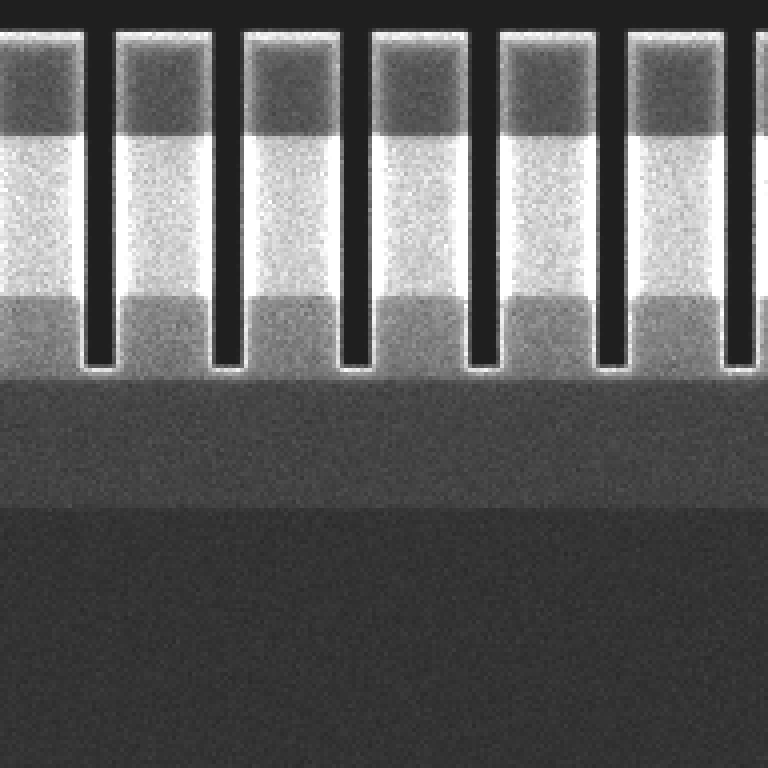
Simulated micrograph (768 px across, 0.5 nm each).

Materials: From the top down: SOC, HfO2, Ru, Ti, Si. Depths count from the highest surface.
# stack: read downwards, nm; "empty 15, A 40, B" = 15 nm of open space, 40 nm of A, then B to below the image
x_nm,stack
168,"SOC 52, HfO2 80, Ru 42, Ti 64, Si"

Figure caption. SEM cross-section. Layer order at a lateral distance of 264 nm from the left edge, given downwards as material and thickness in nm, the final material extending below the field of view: SOC 52, HfO2 80, Ru 42, Ti 64, Si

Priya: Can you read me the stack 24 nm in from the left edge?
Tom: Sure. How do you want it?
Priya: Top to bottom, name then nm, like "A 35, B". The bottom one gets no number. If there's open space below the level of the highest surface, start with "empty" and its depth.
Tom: SOC 52, HfO2 80, Ru 42, Ti 64, Si